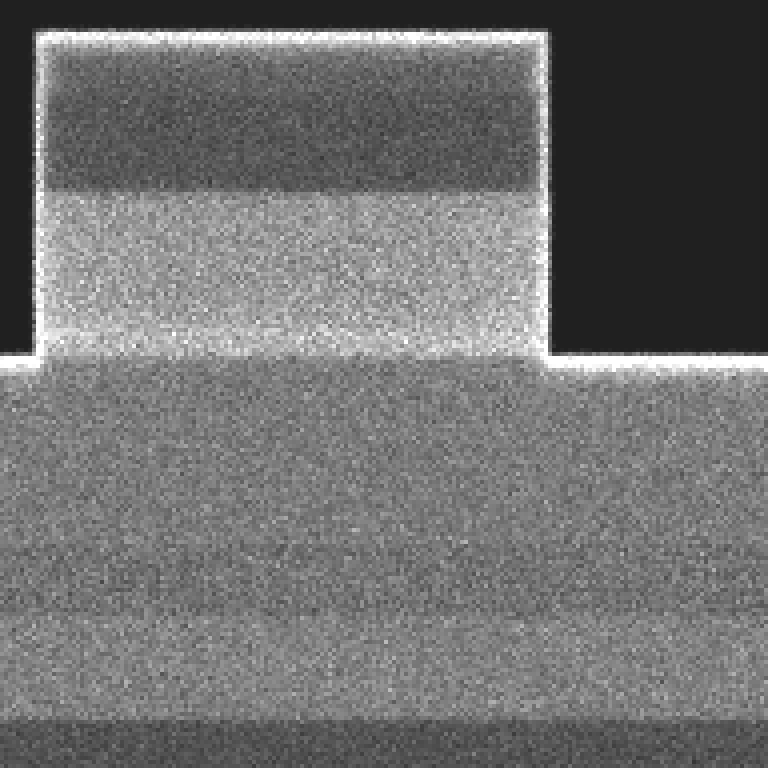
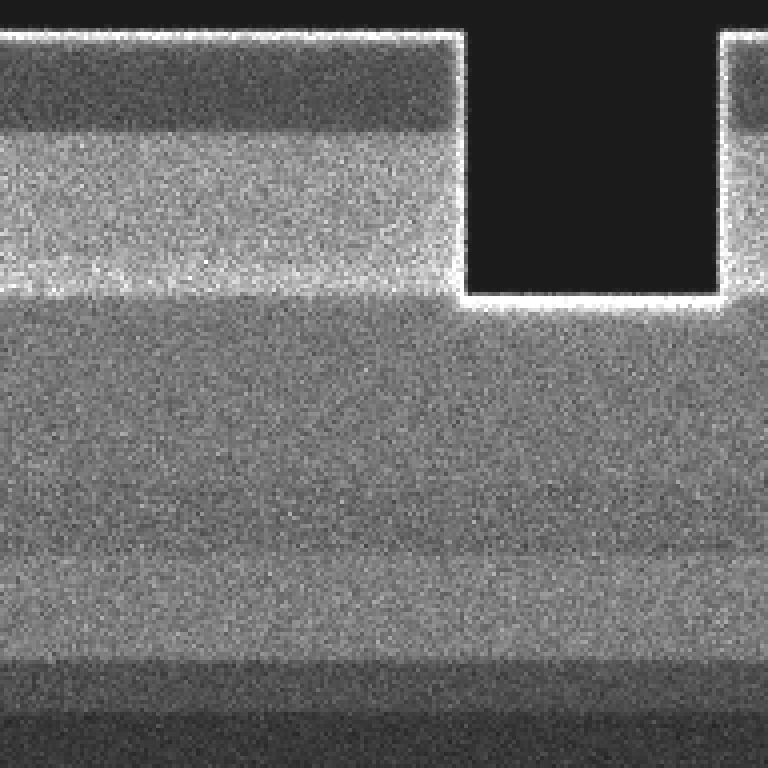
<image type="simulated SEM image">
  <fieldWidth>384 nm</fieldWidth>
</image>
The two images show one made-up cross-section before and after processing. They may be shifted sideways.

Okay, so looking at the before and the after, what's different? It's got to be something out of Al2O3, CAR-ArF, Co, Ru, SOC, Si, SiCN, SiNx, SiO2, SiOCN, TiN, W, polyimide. SOC, removed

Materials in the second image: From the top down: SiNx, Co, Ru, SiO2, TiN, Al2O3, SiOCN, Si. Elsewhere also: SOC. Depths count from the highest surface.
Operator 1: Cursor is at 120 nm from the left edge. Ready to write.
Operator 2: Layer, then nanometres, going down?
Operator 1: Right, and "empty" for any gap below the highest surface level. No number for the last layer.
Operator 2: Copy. SiNx 50, Co 66, Ru 16, SiO2 94, TiN 36, Al2O3 52, SiOCN 26, Si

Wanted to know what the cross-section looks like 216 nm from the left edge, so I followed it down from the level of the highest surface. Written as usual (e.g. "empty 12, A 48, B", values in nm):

SiNx 50, Co 66, Ru 16, SiO2 94, TiN 36, Al2O3 52, SiOCN 26, Si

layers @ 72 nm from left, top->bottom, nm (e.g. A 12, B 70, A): SiNx 50, Co 66, Ru 16, SiO2 94, TiN 36, Al2O3 52, SiOCN 26, Si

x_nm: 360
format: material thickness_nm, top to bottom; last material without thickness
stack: SiNx 50, Co 66, Ru 16, SiO2 94, TiN 36, Al2O3 52, SiOCN 26, Si